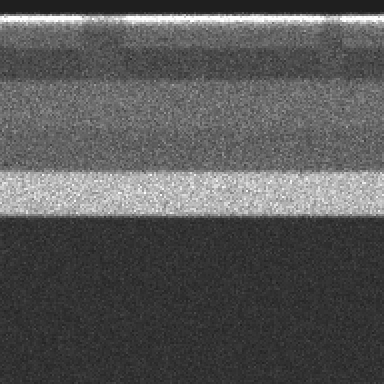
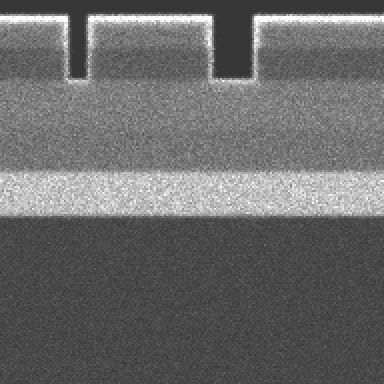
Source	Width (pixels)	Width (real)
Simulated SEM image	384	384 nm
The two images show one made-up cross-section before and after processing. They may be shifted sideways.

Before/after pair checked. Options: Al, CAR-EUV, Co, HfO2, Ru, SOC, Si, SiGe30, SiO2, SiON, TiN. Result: removed SOC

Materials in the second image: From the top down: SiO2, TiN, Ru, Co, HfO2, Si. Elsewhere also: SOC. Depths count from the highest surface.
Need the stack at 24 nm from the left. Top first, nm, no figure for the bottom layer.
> SiO2 32, TiN 32, Ru 48, Co 44, HfO2 44, Si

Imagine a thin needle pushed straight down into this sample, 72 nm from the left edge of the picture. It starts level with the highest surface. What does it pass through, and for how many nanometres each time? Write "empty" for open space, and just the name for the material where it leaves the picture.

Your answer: empty 64, Ru 48, Co 44, HfO2 44, Si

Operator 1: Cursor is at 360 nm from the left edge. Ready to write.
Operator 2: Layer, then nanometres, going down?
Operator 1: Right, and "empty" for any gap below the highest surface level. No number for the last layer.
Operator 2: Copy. SiO2 32, TiN 32, Ru 48, Co 44, HfO2 44, Si